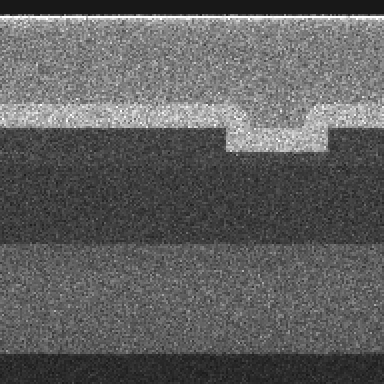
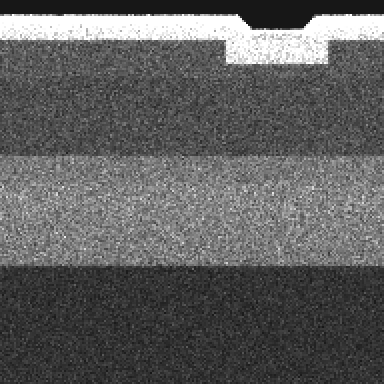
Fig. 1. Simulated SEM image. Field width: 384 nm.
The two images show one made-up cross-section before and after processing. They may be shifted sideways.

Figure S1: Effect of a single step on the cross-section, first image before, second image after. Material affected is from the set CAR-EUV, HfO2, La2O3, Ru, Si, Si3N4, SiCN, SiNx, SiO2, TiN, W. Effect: removed W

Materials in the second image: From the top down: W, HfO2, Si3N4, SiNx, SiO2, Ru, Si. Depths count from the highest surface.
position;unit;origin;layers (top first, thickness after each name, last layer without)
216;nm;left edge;HfO2 24, Si3N4 38, SiNx 78, SiO2 26, Ru 84, Si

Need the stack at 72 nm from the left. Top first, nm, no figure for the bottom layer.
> HfO2 24, Si3N4 38, SiNx 78, SiO2 26, Ru 84, Si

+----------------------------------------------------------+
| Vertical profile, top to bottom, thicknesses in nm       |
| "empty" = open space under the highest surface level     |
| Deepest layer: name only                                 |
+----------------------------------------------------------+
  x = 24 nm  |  HfO2 24, Si3N4 38, SiNx 78, SiO2 26, Ru 84, Si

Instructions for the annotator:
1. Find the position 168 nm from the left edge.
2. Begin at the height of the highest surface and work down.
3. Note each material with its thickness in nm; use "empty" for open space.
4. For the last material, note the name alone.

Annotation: HfO2 24, Si3N4 38, SiNx 78, SiO2 26, Ru 84, Si